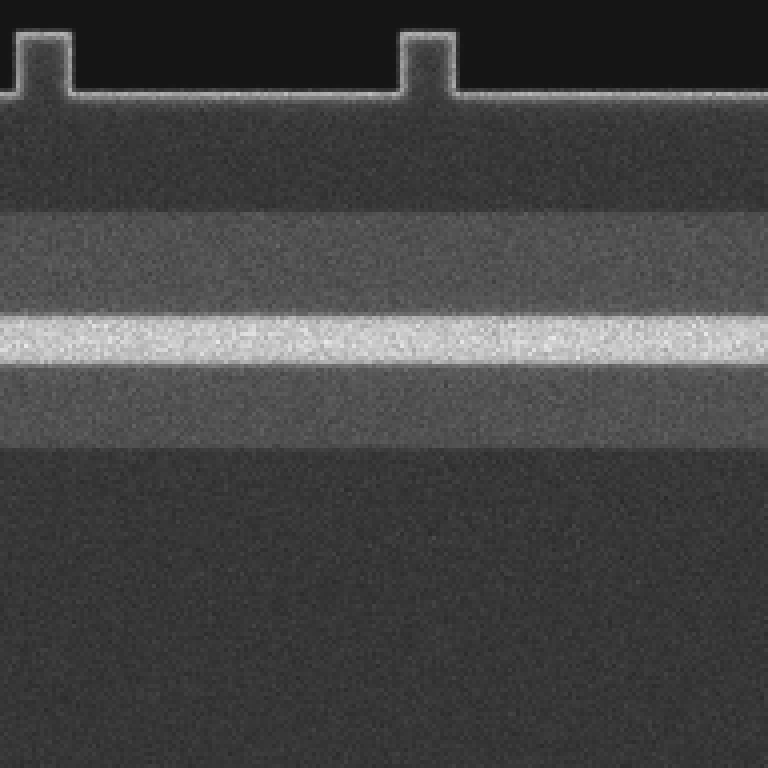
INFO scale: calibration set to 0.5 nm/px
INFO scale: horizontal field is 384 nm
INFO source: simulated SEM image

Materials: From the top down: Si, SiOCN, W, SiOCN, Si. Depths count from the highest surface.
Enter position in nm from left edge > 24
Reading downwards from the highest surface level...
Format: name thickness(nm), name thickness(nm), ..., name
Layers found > Si 90, SiOCN 52, W 24, SiOCN 42, Si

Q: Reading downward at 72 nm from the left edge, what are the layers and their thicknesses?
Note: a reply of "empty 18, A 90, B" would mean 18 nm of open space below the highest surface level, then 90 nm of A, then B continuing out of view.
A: empty 30, Si 60, SiOCN 52, W 24, SiOCN 42, Si